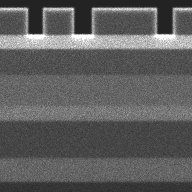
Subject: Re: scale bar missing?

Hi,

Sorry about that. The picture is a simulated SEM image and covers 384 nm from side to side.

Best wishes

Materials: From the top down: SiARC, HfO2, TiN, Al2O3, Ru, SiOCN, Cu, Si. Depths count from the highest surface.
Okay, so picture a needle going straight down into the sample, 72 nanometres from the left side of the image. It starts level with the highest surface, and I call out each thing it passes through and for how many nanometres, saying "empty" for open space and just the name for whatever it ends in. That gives empty 54, HfO2 28, TiN 52, Al2O3 62, Ru 30, SiOCN 74, Cu 48, Si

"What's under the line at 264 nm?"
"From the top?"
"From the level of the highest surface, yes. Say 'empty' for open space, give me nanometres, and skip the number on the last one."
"SiARC 54, HfO2 28, TiN 52, Al2O3 62, Ru 30, SiOCN 74, Cu 48, Si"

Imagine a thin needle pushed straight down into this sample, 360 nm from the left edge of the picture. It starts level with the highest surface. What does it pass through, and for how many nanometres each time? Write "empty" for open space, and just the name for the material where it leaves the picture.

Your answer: SiARC 54, HfO2 28, TiN 52, Al2O3 62, Ru 30, SiOCN 74, Cu 48, Si